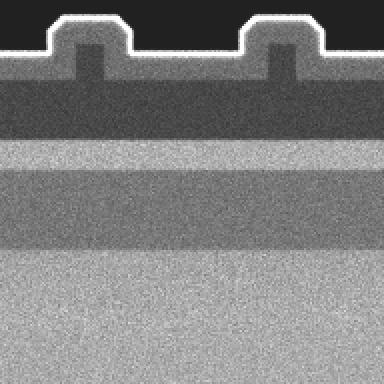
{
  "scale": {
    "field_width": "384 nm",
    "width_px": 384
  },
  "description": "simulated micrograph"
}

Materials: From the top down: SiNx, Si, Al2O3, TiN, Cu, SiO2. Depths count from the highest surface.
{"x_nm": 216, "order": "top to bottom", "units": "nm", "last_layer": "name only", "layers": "empty 36, SiNx 28, Si 60, Al2O3 30, TiN 80, Cu 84, SiO2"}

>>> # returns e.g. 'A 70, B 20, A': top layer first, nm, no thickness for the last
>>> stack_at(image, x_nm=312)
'empty 4, SiNx 60, Si 60, Al2O3 30, TiN 80, Cu 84, SiO2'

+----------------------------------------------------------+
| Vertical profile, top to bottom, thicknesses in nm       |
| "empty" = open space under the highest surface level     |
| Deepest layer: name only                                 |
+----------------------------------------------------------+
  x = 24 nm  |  empty 36, SiNx 28, Si 60, Al2O3 30, TiN 80, Cu 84, SiO2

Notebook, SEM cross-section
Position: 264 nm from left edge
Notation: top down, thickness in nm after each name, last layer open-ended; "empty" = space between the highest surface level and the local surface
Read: SiNx 64, Si 60, Al2O3 30, TiN 80, Cu 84, SiO2